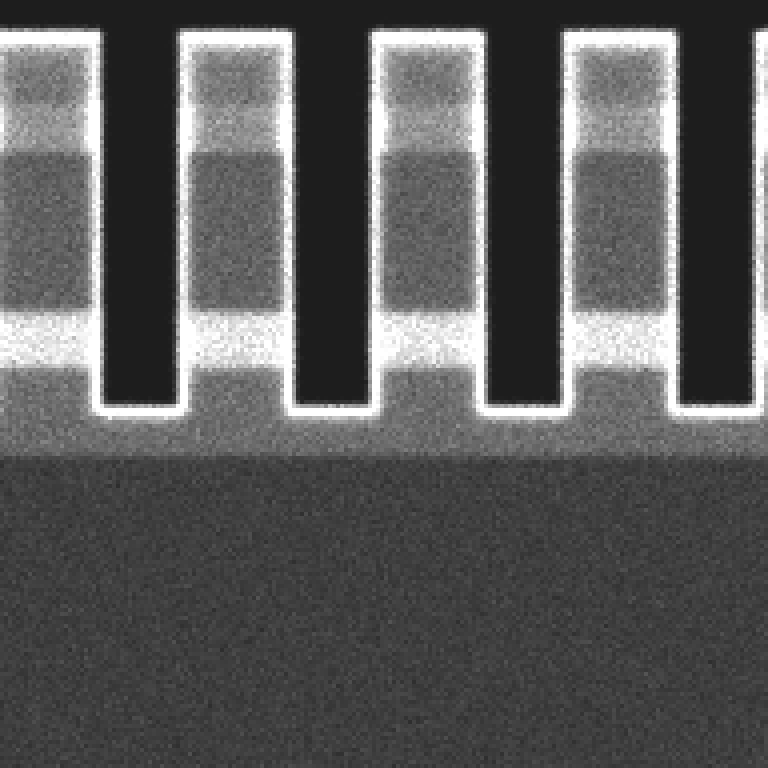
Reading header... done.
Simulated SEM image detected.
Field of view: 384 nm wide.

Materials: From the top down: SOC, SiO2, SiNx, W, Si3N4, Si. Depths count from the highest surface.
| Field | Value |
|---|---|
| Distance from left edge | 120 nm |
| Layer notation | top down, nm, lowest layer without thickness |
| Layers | SOC 36, SiO2 24, SiNx 80, W 28, Si3N4 44, Si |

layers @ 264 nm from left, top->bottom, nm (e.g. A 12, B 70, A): empty 188, Si3N4 24, Si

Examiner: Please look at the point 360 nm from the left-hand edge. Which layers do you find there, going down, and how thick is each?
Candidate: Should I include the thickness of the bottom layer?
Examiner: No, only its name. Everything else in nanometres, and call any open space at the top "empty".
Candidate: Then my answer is empty 188, Si3N4 24, Si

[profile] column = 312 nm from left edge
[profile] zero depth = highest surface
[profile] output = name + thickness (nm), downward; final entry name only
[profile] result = SOC 36, SiO2 24, SiNx 80, W 28, Si3N4 44, Si